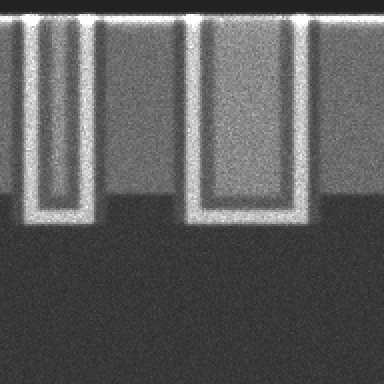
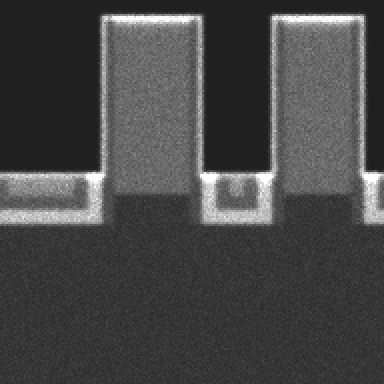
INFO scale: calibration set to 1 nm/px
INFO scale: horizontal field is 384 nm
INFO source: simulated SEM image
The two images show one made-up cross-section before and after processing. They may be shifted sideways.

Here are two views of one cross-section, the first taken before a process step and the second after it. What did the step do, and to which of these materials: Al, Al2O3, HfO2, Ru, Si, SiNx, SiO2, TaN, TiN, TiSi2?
It removed HfO2 and Ru and TiN.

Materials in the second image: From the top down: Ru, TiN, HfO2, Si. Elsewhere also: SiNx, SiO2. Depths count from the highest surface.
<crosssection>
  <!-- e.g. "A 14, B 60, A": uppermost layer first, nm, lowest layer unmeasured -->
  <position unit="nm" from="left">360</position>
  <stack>SiNx 208, Si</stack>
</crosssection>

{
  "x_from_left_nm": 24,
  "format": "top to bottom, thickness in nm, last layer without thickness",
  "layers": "empty 158, Ru 22, TiN 14, HfO2 14, Si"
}